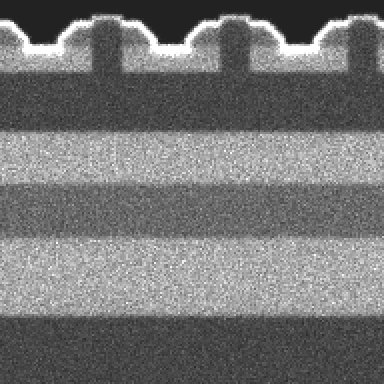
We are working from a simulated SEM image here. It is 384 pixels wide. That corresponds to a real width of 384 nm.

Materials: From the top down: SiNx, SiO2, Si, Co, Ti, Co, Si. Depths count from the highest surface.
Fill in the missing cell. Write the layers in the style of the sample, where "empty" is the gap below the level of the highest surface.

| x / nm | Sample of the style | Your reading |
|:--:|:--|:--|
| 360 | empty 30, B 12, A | Si 116, Co 52, Ti 54, Co 78, Si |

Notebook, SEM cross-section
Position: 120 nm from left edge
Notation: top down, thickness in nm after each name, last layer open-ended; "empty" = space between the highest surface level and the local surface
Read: Si 116, Co 52, Ti 54, Co 78, Si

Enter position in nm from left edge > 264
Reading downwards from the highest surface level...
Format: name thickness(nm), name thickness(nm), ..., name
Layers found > empty 6, SiNx 24, SiO2 26, Si 60, Co 52, Ti 54, Co 78, Si